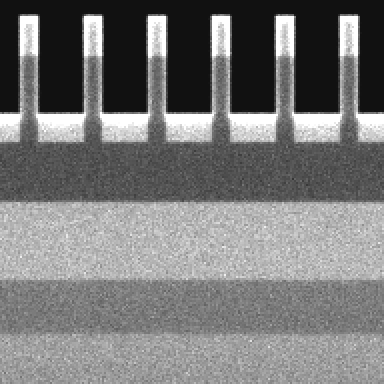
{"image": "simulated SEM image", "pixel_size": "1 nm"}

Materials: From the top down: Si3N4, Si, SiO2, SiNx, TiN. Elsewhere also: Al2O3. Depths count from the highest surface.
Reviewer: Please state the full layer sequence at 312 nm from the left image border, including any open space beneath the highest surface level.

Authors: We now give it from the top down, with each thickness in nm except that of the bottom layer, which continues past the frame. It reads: empty 98, Al2O3 28, Si 60, SiO2 78, SiNx 54, TiN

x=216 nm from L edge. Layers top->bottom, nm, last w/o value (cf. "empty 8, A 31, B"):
Si3N4 40, Si 146, SiO2 78, SiNx 54, TiN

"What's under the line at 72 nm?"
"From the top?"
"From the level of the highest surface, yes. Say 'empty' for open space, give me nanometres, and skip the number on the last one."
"empty 98, Al2O3 28, Si 60, SiO2 78, SiNx 54, TiN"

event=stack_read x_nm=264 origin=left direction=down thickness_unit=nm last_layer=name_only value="empty 98, Al2O3 28, Si 60, SiO2 78, SiNx 54, TiN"